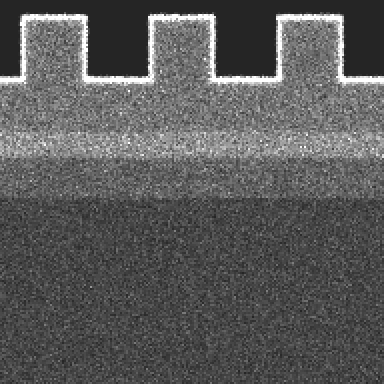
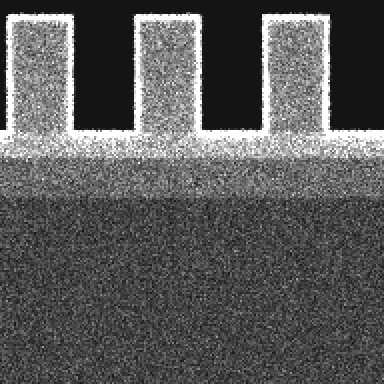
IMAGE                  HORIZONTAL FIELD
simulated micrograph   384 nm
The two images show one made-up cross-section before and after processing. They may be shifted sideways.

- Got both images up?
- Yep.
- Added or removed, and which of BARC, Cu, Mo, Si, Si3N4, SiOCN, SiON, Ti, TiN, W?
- removed, Si3N4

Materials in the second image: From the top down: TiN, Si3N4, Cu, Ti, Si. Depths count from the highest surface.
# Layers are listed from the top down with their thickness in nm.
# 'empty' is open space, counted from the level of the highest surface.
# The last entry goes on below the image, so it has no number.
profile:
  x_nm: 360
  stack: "empty 116, Cu 26, Ti 40, Si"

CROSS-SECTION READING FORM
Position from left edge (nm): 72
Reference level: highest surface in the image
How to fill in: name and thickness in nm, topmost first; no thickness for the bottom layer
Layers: empty 116, Cu 26, Ti 40, Si